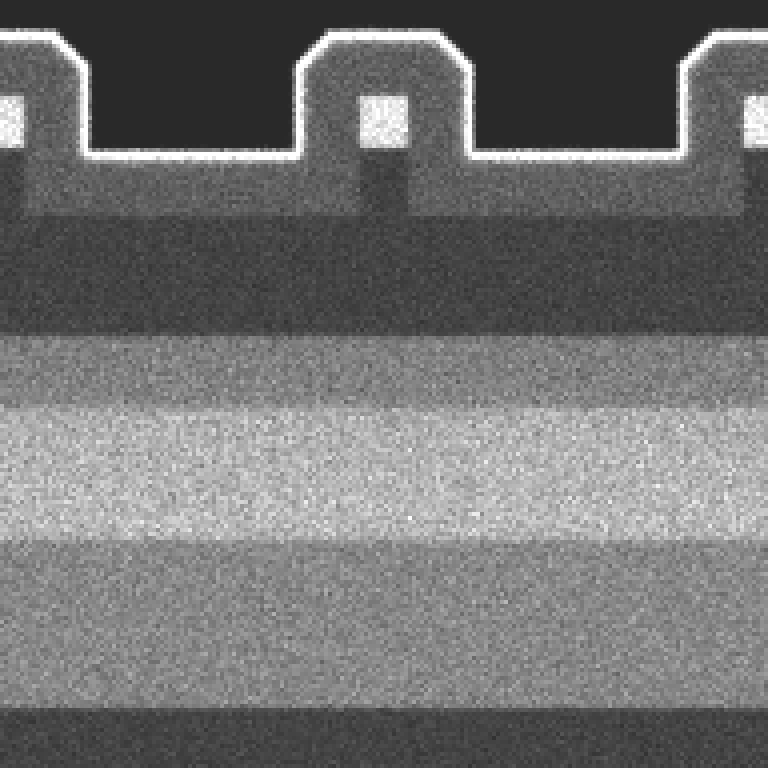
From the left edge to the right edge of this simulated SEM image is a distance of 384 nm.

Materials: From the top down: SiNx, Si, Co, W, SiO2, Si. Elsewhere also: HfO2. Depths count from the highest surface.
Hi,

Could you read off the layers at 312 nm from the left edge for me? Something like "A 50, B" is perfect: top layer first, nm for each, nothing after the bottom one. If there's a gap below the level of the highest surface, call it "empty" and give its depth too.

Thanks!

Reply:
empty 60, SiNx 32, Si 60, Co 36, W 66, SiO2 84, Si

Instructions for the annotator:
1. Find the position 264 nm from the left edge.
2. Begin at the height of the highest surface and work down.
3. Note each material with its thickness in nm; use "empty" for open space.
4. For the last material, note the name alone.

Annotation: empty 60, SiNx 32, Si 60, Co 36, W 66, SiO2 84, Si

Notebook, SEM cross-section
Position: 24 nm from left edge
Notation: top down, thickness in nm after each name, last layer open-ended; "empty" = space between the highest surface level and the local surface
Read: SiNx 92, Si 60, Co 36, W 66, SiO2 84, Si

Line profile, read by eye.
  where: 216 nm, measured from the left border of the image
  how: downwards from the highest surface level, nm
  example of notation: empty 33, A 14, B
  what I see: SiNx 92, Si 60, Co 36, W 66, SiO2 84, Si